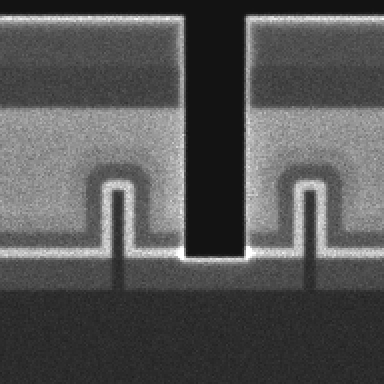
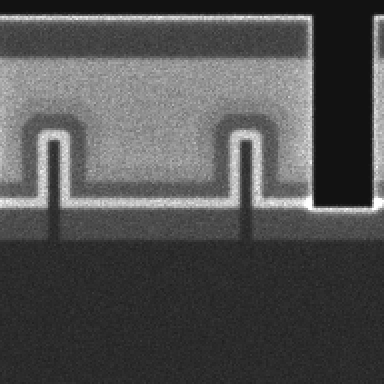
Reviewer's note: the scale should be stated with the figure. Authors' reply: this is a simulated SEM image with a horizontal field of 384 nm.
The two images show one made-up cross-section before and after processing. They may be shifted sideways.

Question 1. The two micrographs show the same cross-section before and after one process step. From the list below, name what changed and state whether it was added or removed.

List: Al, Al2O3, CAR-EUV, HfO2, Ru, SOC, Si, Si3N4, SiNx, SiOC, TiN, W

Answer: SOC, removed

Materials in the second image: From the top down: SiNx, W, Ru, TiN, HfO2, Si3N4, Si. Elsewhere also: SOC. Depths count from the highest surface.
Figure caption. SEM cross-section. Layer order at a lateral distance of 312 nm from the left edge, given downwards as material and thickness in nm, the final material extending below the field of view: empty 192, Si3N4 32, Si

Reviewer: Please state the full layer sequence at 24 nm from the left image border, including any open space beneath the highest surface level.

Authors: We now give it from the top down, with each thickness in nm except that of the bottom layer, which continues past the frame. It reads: SiNx 42, W 42, Ru 24, TiN 74, HfO2 10, Si3N4 32, Si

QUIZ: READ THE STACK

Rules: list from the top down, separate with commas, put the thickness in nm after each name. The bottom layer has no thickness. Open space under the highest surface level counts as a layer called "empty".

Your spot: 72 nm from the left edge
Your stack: SiNx 42, W 40, Ru 16, TiN 84, HfO2 10, Si3N4 32, Si